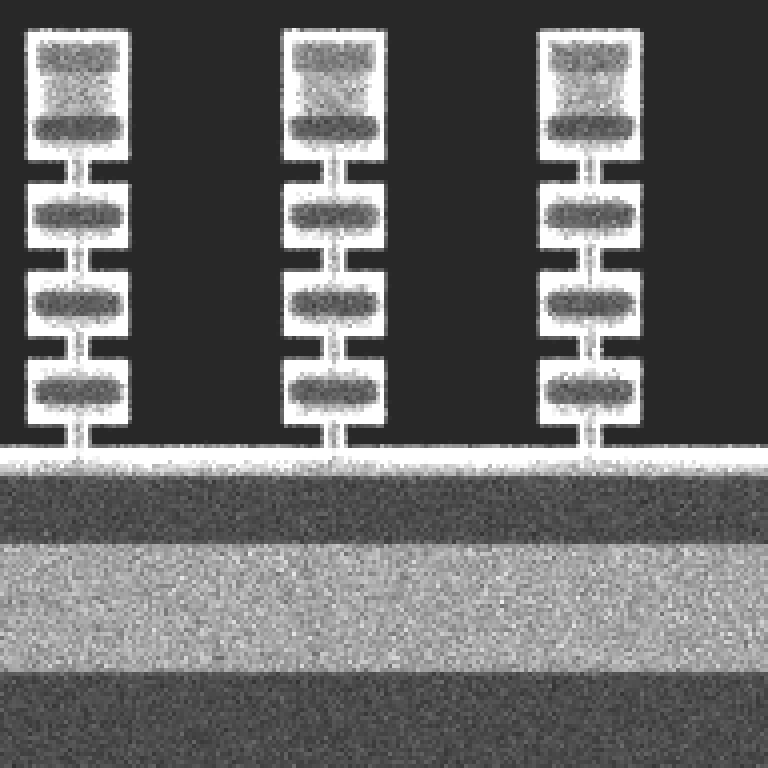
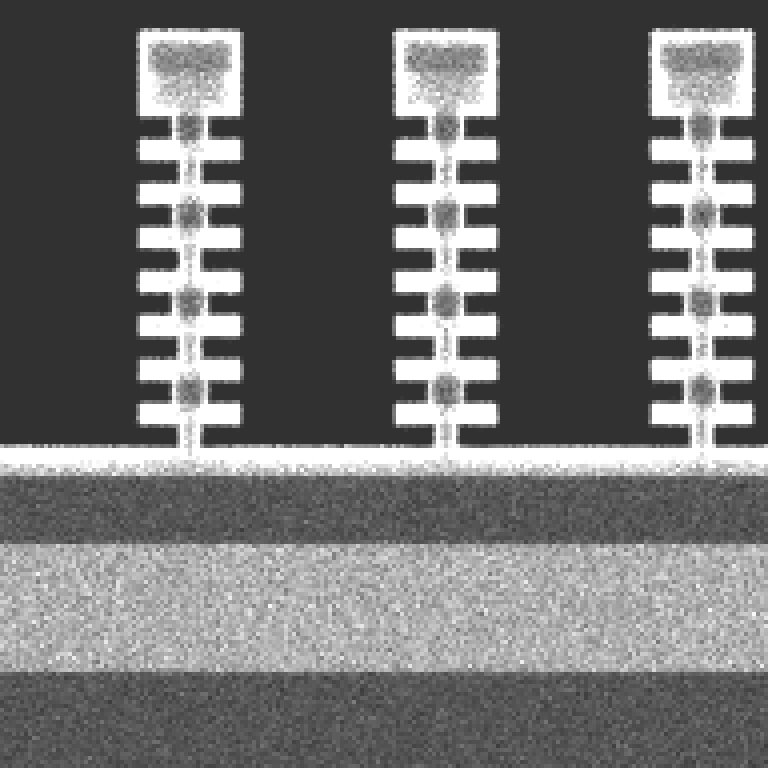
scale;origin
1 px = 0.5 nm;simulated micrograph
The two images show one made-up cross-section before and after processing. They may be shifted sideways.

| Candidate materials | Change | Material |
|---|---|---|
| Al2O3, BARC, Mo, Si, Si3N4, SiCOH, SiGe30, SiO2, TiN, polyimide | removed | SiGe30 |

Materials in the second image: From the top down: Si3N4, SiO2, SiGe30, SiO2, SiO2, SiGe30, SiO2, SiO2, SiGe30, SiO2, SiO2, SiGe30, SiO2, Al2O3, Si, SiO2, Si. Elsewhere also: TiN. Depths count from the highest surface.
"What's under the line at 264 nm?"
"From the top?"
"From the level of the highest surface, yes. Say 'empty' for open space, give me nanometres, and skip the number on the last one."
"empty 208, Al2O3 14, Si 34, SiO2 64, Si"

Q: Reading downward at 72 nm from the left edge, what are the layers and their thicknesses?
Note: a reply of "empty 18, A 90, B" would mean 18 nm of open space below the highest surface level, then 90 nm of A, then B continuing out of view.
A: Si3N4 20, SiO2 22, empty 12, SiO2 10, empty 12, SiO2 10, empty 12, SiO2 10, empty 12, SiO2 10, empty 12, SiO2 10, empty 12, SiO2 10, empty 12, SiO2 10, empty 12, Al2O3 14, Si 34, SiO2 64, Si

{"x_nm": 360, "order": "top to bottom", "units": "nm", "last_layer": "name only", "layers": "Si3N4 20, SiO2 22, empty 12, SiO2 10, empty 12, SiO2 10, empty 12, SiO2 10, empty 12, SiO2 10, empty 12, SiO2 10, empty 12, SiO2 10, empty 12, SiO2 10, empty 12, Al2O3 14, Si 34, SiO2 64, Si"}